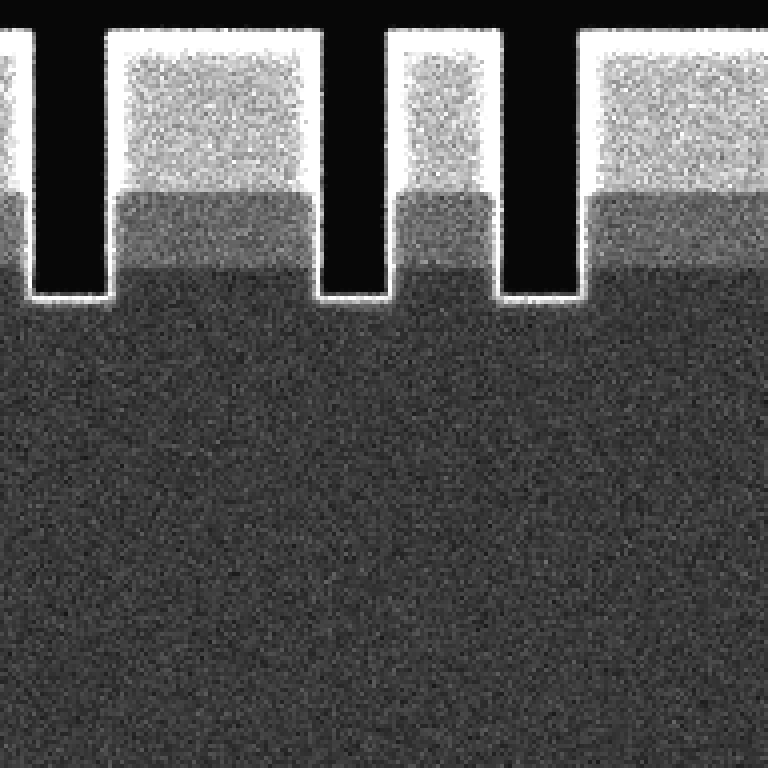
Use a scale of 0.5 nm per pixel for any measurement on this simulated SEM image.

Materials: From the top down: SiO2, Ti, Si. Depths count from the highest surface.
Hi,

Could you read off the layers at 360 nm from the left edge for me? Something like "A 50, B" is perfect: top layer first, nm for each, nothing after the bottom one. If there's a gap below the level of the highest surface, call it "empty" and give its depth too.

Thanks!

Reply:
SiO2 80, Ti 38, Si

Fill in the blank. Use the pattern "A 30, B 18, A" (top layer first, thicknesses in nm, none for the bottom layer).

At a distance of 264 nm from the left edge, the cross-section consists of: empty 132, Si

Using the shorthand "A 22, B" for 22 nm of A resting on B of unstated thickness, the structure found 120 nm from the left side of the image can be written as SiO2 80, Ti 38, Si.